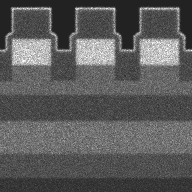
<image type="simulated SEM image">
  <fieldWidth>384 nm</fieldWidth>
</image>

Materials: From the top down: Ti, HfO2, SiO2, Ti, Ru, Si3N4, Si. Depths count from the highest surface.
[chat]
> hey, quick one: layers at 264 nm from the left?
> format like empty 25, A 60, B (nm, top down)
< empty 84, Ti 62, SiO2 28, Ti 52, Ru 66, Si3N4 48, Si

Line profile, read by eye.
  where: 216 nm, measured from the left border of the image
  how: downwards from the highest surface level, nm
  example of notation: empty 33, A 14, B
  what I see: Ti 62, HfO2 52, SiO2 60, Ti 52, Ru 66, Si3N4 48, Si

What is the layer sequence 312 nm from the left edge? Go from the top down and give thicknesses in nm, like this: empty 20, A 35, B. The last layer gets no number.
Ti 62, HfO2 52, SiO2 60, Ti 52, Ru 66, Si3N4 48, Si